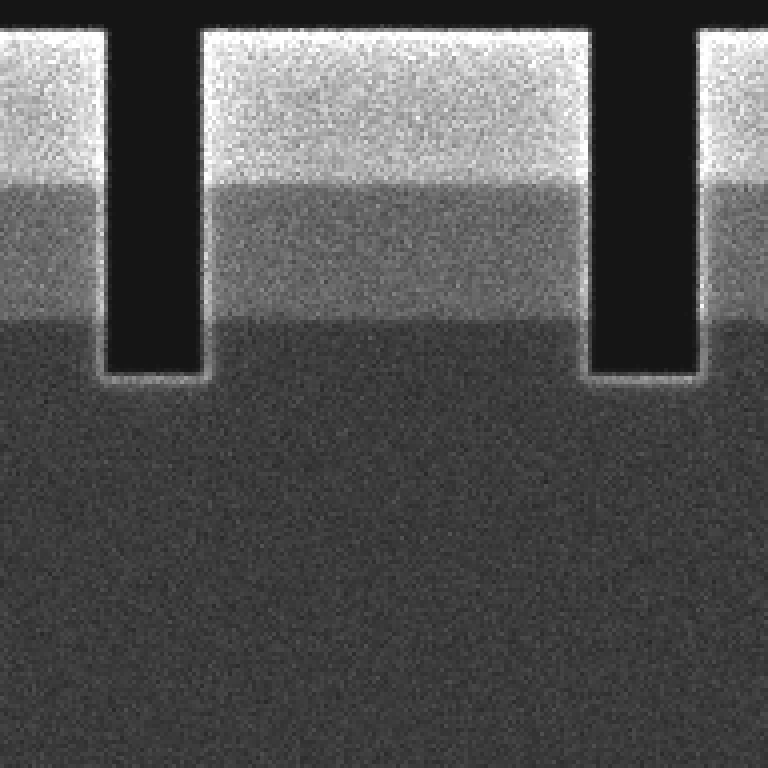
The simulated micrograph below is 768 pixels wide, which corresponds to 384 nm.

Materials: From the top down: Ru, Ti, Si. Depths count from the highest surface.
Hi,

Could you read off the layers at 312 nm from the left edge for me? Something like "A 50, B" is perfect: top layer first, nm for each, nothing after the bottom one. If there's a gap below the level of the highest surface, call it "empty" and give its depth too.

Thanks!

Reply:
empty 172, Si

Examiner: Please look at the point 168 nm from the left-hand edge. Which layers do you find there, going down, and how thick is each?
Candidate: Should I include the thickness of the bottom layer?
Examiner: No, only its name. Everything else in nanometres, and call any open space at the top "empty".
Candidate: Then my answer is Ru 76, Ti 68, Si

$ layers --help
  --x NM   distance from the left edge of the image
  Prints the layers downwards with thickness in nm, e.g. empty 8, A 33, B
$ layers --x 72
empty 172, Si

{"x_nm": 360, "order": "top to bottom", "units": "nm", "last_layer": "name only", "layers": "Ru 76, Ti 68, Si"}